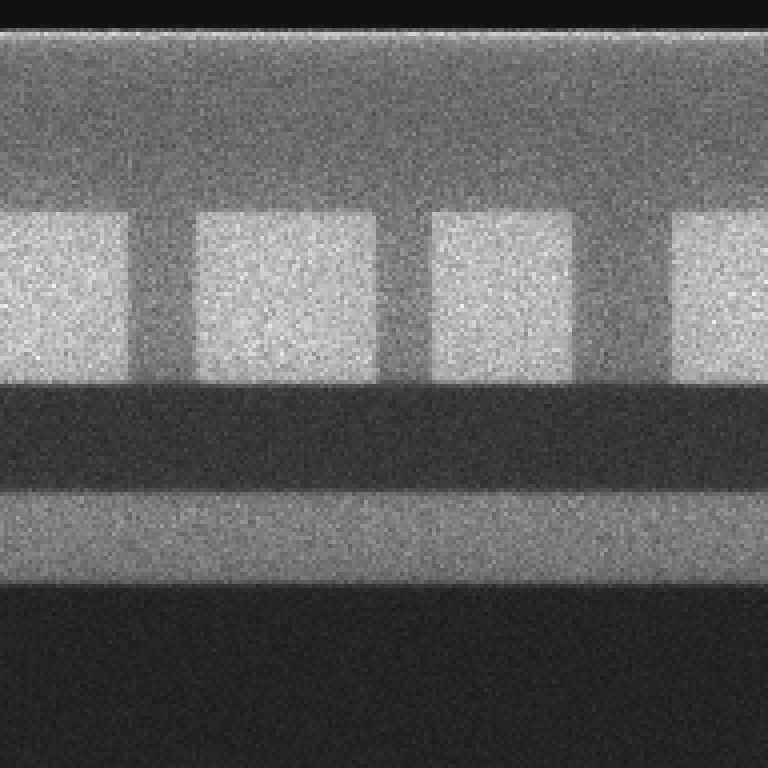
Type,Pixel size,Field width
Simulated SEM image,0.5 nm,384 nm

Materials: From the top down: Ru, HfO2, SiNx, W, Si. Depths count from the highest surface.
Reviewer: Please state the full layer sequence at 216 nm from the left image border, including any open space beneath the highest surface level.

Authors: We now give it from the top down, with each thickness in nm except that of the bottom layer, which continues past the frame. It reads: Ru 90, HfO2 86, SiNx 54, W 46, Si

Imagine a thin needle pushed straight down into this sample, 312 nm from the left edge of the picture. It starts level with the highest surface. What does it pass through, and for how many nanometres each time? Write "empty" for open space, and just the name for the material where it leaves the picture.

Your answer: Ru 176, SiNx 54, W 46, Si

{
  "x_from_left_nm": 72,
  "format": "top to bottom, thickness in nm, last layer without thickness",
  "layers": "Ru 176, SiNx 54, W 46, Si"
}